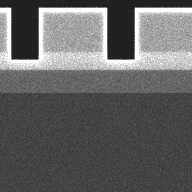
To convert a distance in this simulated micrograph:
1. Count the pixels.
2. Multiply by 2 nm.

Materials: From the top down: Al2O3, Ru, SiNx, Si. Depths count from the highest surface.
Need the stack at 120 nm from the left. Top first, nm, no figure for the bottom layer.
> Al2O3 88, Ru 36, SiNx 46, Si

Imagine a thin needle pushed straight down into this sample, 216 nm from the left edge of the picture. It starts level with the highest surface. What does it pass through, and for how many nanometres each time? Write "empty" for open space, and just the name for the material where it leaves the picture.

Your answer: empty 104, Ru 20, SiNx 46, Si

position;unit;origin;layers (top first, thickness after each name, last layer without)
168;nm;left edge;Al2O3 88, Ru 36, SiNx 46, Si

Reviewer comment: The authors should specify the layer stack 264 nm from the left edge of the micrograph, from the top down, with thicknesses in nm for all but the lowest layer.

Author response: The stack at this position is empty 104, Ru 20, SiNx 46, Si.